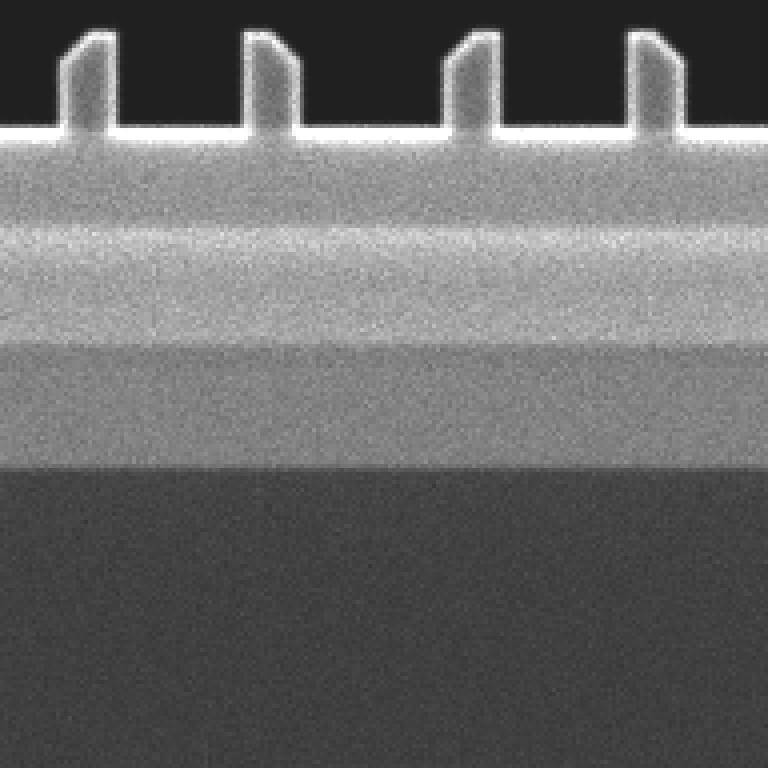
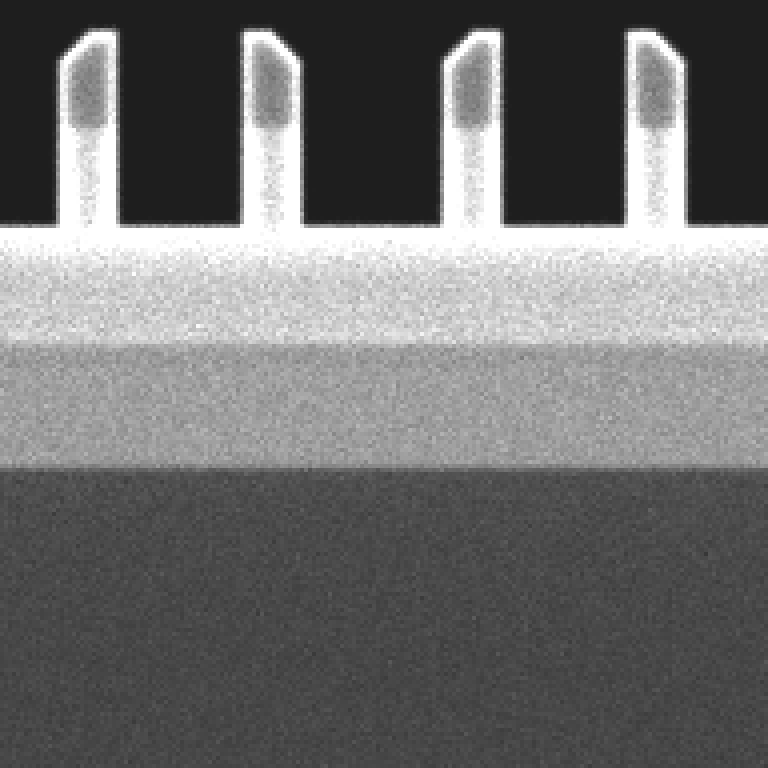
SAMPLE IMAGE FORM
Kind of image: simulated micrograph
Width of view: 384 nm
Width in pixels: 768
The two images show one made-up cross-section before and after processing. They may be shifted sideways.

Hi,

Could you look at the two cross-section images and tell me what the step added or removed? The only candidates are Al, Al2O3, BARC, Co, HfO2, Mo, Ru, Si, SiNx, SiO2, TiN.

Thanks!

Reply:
removed Al2O3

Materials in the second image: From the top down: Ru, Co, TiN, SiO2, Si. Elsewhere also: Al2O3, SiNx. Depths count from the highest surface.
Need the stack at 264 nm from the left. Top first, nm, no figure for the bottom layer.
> empty 98, Ru 42, Co 16, TiN 12, SiO2 50, Si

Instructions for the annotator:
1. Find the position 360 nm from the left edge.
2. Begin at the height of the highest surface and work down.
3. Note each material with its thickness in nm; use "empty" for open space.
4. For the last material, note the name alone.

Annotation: empty 98, Ru 42, Co 16, TiN 12, SiO2 50, Si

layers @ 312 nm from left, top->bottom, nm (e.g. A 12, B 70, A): empty 98, Ru 42, Co 16, TiN 12, SiO2 50, Si